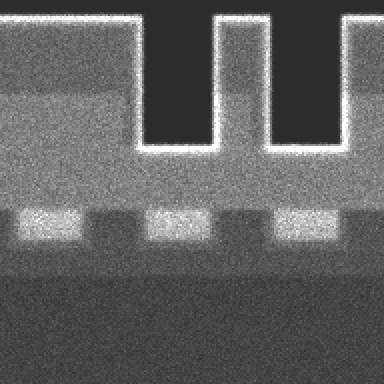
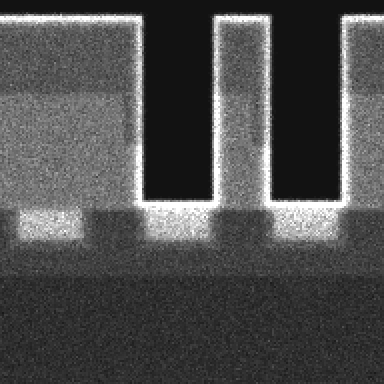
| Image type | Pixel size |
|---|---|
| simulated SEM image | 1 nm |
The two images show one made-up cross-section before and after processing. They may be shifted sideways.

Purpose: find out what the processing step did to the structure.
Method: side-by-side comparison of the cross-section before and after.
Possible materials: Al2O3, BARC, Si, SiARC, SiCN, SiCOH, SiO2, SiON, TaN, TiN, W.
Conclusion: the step removed SiO2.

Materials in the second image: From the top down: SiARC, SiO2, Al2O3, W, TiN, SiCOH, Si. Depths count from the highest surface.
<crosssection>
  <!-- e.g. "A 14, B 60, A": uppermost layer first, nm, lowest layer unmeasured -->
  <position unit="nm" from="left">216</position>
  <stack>SiARC 78, SiO2 108, Al2O3 8, TiN 40, SiCOH 26, Si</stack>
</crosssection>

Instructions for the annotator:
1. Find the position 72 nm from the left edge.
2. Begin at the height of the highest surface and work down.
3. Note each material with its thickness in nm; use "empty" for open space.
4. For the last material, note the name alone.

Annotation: SiARC 78, SiO2 108, Al2O3 8, W 30, TiN 10, SiCOH 26, Si